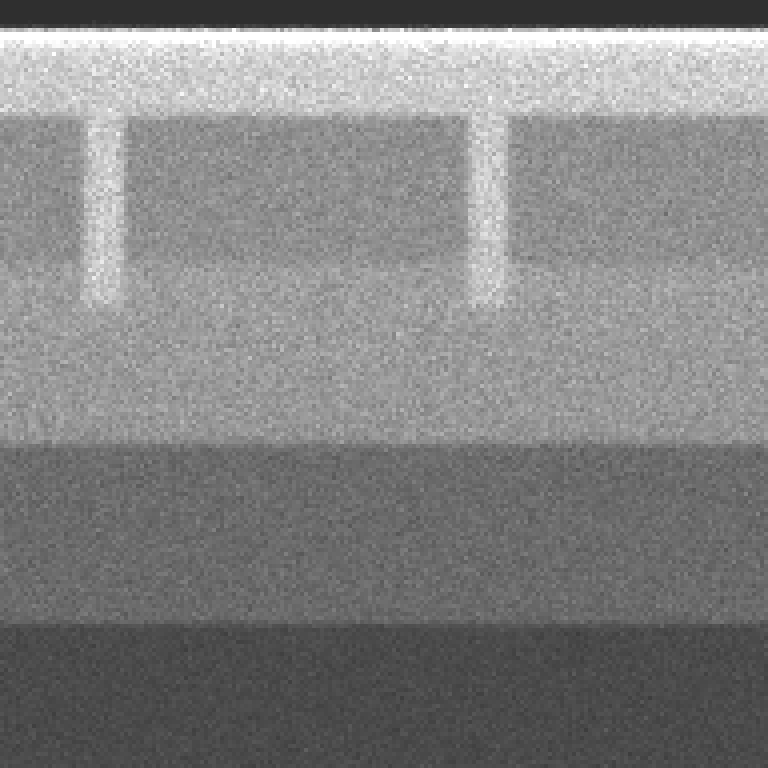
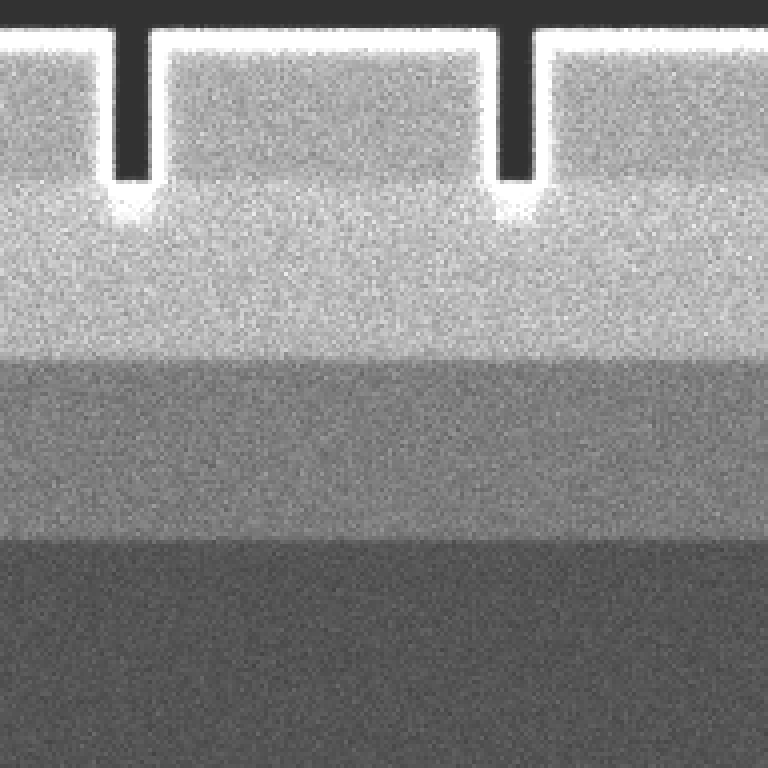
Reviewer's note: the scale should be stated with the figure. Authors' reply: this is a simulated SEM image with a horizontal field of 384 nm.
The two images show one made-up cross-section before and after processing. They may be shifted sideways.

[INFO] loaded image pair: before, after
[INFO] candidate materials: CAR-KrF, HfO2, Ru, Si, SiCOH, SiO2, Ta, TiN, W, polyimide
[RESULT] removed W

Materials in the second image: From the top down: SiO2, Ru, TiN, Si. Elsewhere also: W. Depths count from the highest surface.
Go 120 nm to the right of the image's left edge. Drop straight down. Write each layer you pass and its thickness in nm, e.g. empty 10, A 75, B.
SiO2 74, Ru 90, TiN 90, Si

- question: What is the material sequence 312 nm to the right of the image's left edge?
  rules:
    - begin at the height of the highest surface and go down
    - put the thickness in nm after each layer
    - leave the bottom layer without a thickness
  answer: SiO2 74, Ru 90, TiN 90, Si